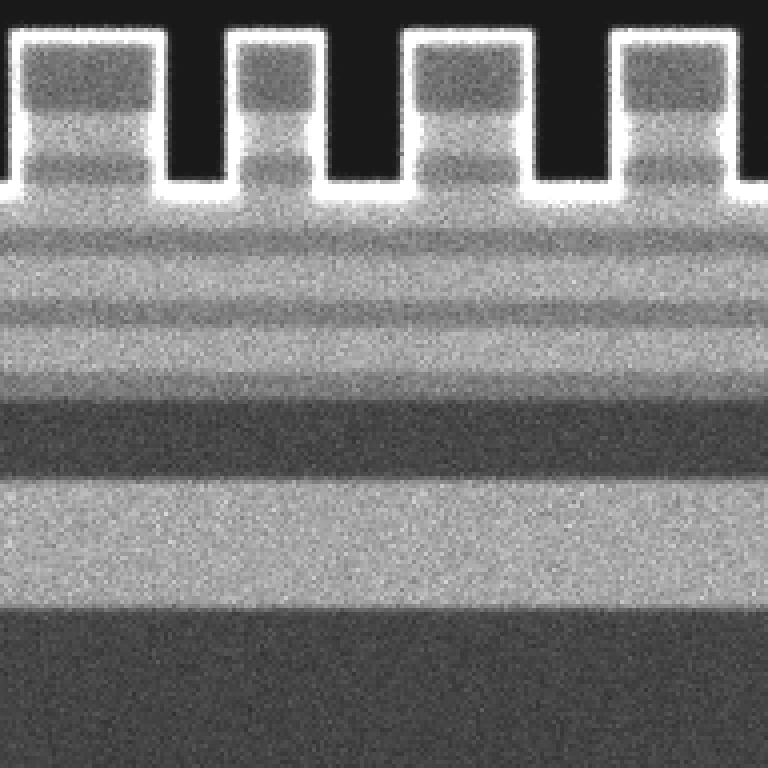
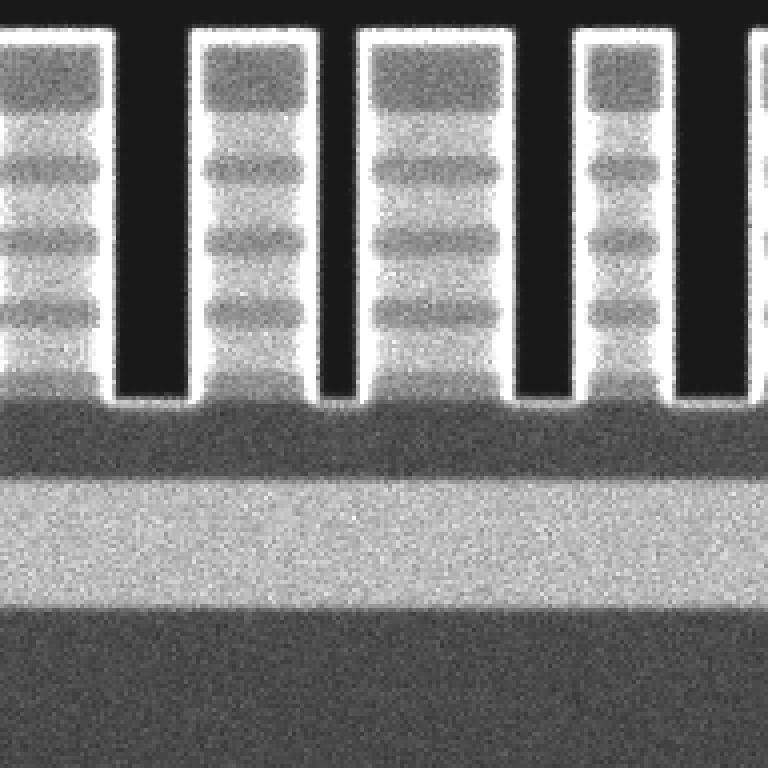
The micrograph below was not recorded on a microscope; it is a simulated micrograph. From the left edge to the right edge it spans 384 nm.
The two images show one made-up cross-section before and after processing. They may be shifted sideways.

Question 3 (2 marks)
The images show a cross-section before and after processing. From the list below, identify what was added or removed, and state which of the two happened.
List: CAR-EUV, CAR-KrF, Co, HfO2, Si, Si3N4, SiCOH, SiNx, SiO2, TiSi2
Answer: Si3N4 and SiO2 was removed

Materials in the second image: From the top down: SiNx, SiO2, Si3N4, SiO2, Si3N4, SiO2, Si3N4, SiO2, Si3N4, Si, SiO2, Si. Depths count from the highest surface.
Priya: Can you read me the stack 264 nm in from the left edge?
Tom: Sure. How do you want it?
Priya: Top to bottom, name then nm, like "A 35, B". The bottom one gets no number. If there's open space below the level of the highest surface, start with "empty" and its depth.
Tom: empty 184, Si 40, SiO2 64, Si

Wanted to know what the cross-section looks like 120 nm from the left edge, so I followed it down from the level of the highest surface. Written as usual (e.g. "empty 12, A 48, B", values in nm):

SiNx 40, SiO2 22, Si3N4 14, SiO2 22, Si3N4 14, SiO2 22, Si3N4 14, SiO2 22, Si3N4 14, Si 40, SiO2 64, Si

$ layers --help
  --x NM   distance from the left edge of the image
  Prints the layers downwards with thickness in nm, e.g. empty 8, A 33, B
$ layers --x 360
empty 184, Si 40, SiO2 64, Si